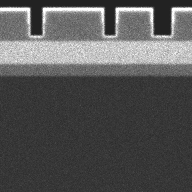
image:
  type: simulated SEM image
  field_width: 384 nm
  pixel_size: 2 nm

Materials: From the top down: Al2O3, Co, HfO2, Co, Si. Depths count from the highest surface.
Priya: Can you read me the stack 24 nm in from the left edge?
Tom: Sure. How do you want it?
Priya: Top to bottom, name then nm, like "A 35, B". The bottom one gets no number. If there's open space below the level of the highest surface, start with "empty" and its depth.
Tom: Al2O3 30, Co 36, HfO2 46, Co 24, Si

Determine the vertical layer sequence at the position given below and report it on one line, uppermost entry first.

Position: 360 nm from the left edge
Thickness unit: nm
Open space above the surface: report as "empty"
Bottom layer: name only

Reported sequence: Al2O3 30, Co 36, HfO2 46, Co 24, Si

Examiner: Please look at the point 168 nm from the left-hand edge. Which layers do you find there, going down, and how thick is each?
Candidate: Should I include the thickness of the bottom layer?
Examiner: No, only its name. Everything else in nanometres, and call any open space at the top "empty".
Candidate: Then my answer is Al2O3 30, Co 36, HfO2 46, Co 24, Si